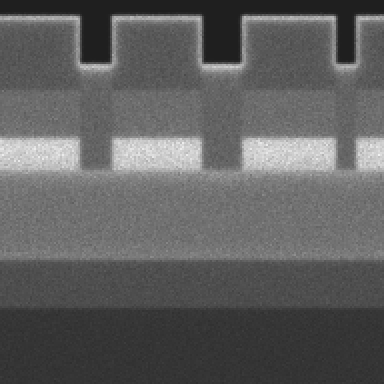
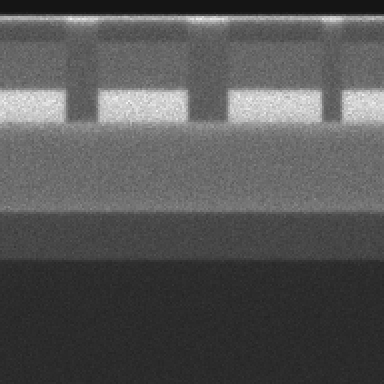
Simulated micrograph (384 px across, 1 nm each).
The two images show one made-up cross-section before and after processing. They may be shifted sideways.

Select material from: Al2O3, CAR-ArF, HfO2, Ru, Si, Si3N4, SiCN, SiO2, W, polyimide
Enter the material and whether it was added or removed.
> Si3N4 / removed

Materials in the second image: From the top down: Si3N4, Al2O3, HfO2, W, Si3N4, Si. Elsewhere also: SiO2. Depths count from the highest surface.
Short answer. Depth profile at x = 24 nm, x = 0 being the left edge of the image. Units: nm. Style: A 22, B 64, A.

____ Si3N4 26, Al2O3 48, HfO2 32, W 90, Si3N4 48, Si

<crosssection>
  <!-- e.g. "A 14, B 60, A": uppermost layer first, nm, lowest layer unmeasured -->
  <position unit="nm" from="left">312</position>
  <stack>Si3N4 26, Al2O3 48, HfO2 32, W 90, Si3N4 48, Si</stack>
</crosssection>